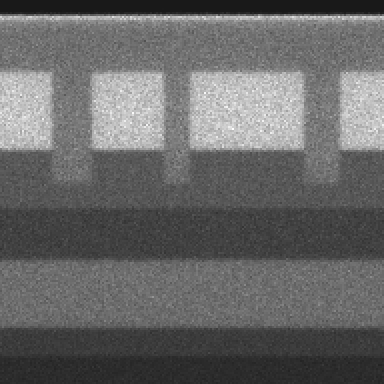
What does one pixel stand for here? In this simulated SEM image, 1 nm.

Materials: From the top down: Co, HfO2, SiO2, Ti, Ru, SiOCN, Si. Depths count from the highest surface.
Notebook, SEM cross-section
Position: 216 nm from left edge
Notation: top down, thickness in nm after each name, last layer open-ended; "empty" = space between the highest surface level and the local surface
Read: Co 56, HfO2 78, SiO2 58, Ti 52, Ru 68, SiOCN 28, Si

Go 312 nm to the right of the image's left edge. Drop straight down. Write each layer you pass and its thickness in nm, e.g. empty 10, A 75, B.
Co 168, SiO2 24, Ti 52, Ru 68, SiOCN 28, Si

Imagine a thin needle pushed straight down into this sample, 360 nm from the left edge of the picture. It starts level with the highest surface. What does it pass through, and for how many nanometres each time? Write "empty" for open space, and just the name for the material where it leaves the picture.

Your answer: Co 56, HfO2 78, SiO2 58, Ti 52, Ru 68, SiOCN 28, Si